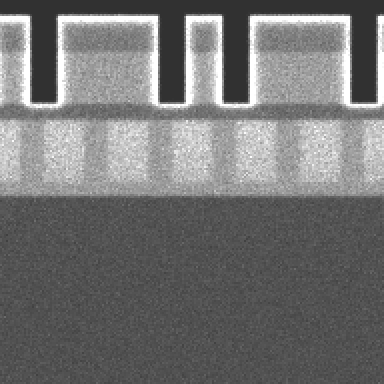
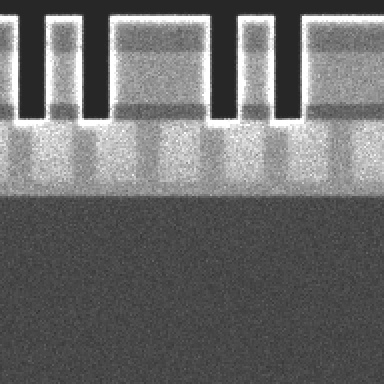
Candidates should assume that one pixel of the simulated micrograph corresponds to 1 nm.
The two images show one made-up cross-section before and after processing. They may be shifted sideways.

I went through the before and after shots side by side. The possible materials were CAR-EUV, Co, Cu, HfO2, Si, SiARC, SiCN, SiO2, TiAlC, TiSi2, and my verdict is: removed, SiCN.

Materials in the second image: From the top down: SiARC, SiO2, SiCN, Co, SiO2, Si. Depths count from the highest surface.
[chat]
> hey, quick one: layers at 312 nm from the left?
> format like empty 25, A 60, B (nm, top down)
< SiARC 36, SiO2 52, SiCN 16, Co 62, SiO2 14, Si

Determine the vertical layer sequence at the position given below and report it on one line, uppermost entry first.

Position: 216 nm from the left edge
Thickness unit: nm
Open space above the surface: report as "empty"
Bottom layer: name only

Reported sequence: empty 104, SiO2 76, Si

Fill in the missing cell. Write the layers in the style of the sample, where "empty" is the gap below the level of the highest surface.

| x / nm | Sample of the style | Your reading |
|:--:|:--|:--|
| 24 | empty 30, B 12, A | empty 104, SiO2 76, Si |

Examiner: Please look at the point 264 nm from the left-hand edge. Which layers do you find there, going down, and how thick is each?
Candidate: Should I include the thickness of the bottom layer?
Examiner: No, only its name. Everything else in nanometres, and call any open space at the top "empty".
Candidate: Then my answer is SiARC 36, SiO2 52, SiCN 16, SiO2 76, Si